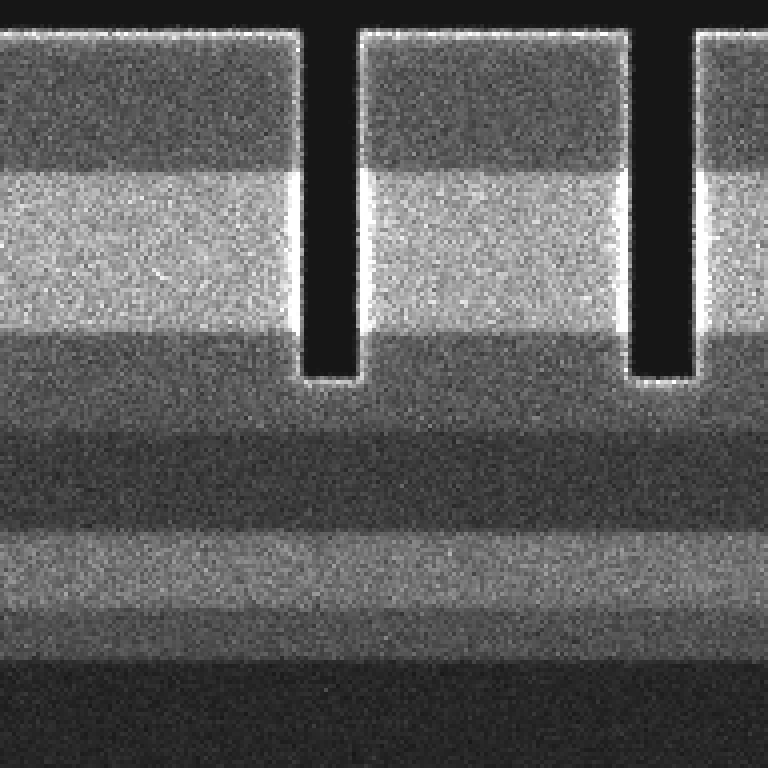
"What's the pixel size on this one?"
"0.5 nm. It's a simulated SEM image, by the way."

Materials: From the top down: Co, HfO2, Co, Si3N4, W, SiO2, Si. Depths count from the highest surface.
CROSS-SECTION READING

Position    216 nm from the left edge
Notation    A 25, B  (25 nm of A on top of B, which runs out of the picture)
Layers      Co 70, HfO2 80, Co 50, Si3N4 50, W 38, SiO2 26, Si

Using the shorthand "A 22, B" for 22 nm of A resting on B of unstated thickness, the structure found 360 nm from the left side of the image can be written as Co 70, HfO2 80, Co 50, Si3N4 50, W 38, SiO2 26, Si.